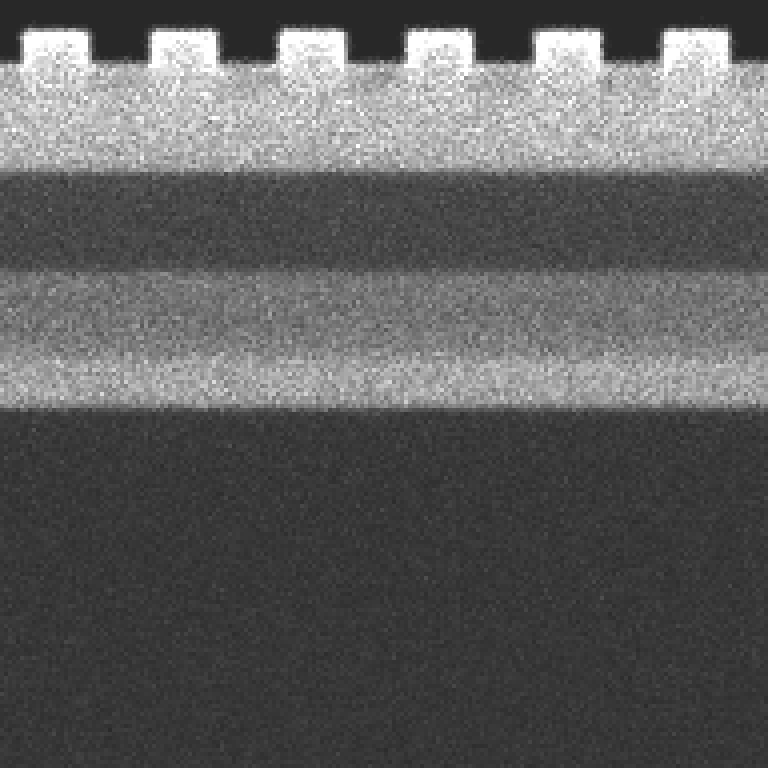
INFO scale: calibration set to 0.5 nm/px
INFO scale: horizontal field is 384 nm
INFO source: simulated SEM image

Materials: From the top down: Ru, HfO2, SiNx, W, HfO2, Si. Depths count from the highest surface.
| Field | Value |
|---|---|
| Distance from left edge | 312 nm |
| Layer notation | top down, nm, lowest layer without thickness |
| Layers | empty 16, Ru 14, HfO2 40, SiNx 50, W 44, HfO2 24, Si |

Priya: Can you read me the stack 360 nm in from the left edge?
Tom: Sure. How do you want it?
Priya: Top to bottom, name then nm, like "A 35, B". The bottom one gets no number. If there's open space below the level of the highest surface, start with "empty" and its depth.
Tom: HfO2 70, SiNx 50, W 44, HfO2 24, Si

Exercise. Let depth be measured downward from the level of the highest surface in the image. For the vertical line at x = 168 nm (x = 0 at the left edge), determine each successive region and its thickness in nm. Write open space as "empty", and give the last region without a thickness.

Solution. HfO2 70, SiNx 50, W 44, HfO2 24, Si